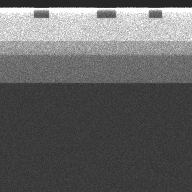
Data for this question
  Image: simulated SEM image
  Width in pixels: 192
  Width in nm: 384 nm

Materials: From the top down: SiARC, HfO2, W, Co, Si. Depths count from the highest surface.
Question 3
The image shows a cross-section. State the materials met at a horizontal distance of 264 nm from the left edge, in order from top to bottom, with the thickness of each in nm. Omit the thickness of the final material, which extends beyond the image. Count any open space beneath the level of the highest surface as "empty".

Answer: HfO2 66, W 28, Co 56, Si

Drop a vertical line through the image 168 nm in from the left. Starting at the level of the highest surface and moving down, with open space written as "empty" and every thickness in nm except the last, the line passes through HfO2 66, W 28, Co 56, Si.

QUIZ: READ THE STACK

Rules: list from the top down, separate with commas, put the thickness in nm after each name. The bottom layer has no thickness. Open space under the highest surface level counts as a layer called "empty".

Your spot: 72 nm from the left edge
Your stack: SiARC 20, HfO2 46, W 28, Co 56, Si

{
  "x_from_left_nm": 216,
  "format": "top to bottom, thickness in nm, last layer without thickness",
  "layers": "SiARC 20, HfO2 46, W 28, Co 56, Si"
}